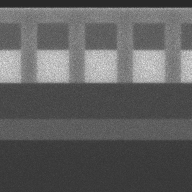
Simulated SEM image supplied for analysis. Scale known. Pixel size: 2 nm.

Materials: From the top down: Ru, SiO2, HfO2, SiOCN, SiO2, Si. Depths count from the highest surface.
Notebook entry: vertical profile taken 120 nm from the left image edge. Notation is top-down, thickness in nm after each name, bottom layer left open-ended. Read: Ru 30, SiO2 54, HfO2 66, SiOCN 72, SiO2 42, Si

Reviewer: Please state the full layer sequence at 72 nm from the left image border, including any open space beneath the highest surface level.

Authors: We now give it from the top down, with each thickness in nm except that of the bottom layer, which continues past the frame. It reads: Ru 150, SiOCN 72, SiO2 42, Si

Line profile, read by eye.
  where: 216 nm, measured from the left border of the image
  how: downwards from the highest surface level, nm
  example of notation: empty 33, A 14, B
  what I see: Ru 30, SiO2 54, HfO2 66, SiOCN 72, SiO2 42, Si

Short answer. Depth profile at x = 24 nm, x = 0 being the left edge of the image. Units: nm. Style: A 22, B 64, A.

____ Ru 30, SiO2 54, HfO2 66, SiOCN 72, SiO2 42, Si